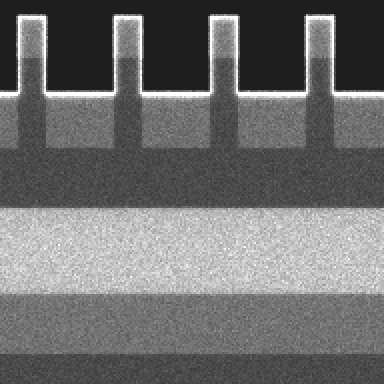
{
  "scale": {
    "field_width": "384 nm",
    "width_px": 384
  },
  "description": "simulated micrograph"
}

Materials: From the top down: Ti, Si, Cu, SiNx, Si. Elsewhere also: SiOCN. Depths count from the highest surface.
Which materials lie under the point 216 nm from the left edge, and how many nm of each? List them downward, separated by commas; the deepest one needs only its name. Ti 42, Si 150, Cu 86, SiNx 60, Si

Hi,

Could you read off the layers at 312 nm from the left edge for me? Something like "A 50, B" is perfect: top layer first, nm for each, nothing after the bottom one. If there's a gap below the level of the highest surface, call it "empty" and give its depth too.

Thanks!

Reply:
Ti 42, Si 150, Cu 86, SiNx 60, Si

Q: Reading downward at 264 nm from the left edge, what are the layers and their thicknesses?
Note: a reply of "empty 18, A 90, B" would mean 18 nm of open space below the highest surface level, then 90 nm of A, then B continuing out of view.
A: empty 76, SiOCN 56, Si 60, Cu 86, SiNx 60, Si